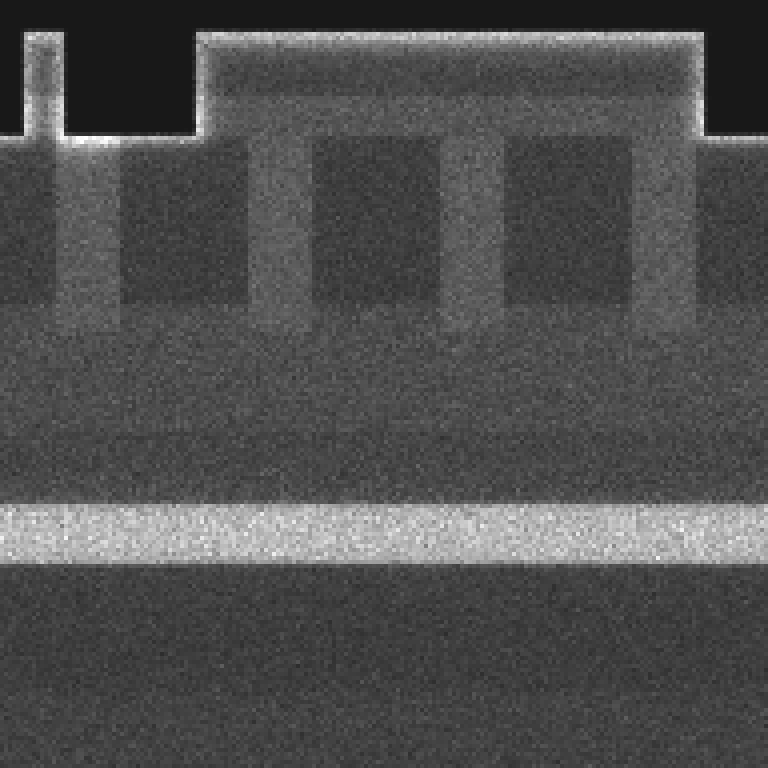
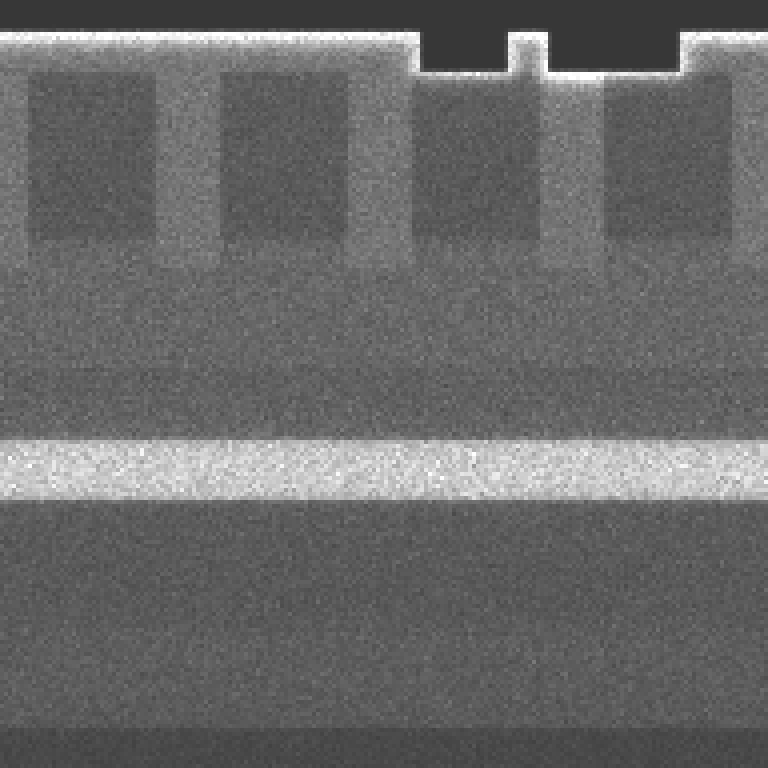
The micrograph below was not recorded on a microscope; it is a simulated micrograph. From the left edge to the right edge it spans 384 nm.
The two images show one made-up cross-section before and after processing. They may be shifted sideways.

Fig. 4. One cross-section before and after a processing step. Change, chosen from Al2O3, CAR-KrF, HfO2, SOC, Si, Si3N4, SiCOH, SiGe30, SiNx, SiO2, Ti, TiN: SOC removed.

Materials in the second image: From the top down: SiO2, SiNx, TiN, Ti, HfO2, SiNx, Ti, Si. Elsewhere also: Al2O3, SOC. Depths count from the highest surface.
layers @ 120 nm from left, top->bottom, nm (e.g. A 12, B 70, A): SiO2 20, SiNx 84, TiN 64, Ti 36, HfO2 30, SiNx 64, Ti 50, Si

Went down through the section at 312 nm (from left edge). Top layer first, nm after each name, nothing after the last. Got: empty 20, SiNx 84, TiN 64, Ti 36, HfO2 30, SiNx 64, Ti 50, Si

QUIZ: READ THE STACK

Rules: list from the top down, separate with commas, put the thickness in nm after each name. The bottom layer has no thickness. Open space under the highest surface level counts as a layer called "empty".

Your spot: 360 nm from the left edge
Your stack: SiO2 20, SiNx 84, TiN 64, Ti 36, HfO2 30, SiNx 64, Ti 50, Si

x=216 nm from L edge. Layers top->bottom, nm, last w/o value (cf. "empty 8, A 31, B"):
empty 20, SiNx 84, TiN 64, Ti 36, HfO2 30, SiNx 64, Ti 50, Si